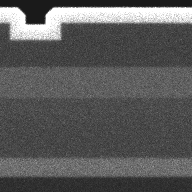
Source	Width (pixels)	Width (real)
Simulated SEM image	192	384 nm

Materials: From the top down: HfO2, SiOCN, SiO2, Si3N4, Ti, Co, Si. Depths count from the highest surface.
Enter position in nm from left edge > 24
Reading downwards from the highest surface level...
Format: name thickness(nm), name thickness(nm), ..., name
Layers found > HfO2 64, SiOCN 54, SiO2 62, Si3N4 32, Ti 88, Co 38, Si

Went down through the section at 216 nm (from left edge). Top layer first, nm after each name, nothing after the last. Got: HfO2 30, SiOCN 88, SiO2 62, Si3N4 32, Ti 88, Co 38, Si